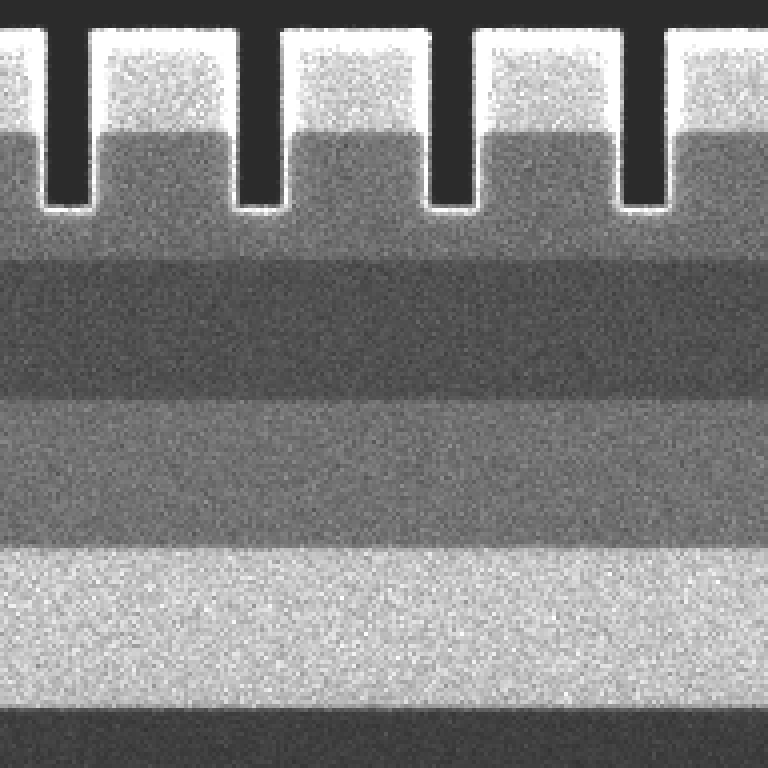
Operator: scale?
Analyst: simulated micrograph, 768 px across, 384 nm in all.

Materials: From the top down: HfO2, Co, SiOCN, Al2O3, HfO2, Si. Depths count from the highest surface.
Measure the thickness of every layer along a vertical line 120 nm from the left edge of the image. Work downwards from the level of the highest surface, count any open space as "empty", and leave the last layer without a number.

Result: empty 88, Co 26, SiOCN 70, Al2O3 74, HfO2 80, Si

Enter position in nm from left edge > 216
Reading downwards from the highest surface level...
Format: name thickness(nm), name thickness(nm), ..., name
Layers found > empty 88, Co 26, SiOCN 70, Al2O3 74, HfO2 80, Si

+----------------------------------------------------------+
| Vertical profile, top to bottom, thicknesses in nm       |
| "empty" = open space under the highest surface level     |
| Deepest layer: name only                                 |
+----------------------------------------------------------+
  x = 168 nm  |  HfO2 50, Co 64, SiOCN 70, Al2O3 74, HfO2 80, Si